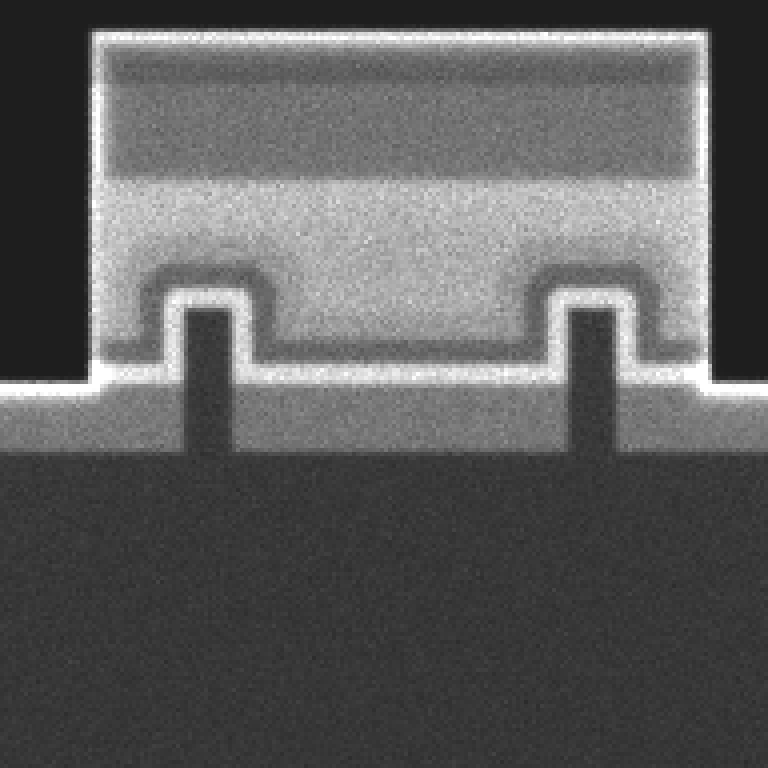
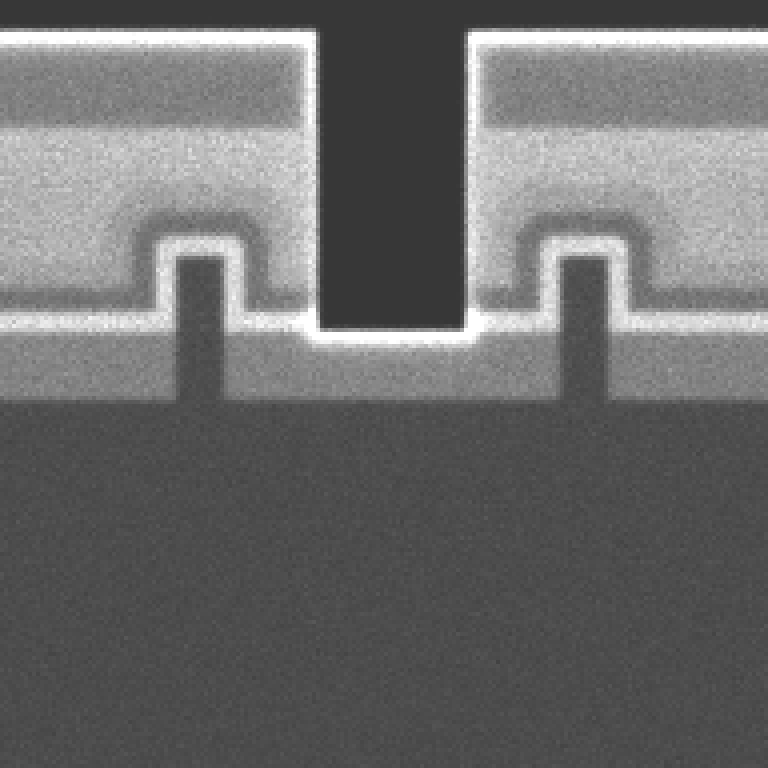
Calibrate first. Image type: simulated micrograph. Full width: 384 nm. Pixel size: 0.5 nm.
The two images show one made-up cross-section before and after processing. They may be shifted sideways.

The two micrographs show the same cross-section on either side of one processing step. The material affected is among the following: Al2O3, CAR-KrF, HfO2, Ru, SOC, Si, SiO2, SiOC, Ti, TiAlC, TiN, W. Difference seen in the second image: SOC removed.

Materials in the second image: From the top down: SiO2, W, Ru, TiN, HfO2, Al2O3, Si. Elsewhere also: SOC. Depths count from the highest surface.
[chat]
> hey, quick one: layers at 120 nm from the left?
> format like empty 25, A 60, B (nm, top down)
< SiO2 48, W 28, Ru 14, TiN 16, HfO2 44, Al2O3 34, Si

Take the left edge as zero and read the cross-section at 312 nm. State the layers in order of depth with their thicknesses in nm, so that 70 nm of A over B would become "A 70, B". SiO2 48, W 28, Ru 14, TiN 16, HfO2 44, Al2O3 34, Si